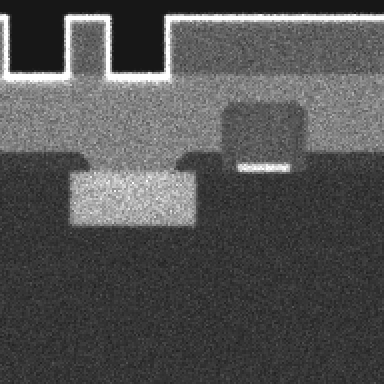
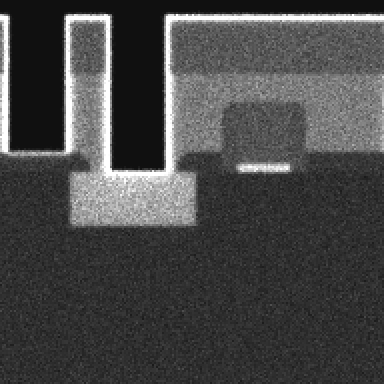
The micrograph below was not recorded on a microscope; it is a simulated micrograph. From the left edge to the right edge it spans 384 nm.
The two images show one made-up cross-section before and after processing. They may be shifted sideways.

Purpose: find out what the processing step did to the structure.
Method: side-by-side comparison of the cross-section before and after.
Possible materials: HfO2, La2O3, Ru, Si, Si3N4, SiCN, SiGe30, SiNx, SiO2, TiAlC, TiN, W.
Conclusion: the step removed SiO2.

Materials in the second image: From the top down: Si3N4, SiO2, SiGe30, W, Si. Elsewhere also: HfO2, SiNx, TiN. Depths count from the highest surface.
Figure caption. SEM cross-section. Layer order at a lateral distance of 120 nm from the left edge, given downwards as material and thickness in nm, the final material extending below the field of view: empty 156, W 54, Si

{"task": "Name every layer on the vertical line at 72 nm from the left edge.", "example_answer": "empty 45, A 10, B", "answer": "Si3N4 58, SiO2 78, SiGe30 20, W 54, Si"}